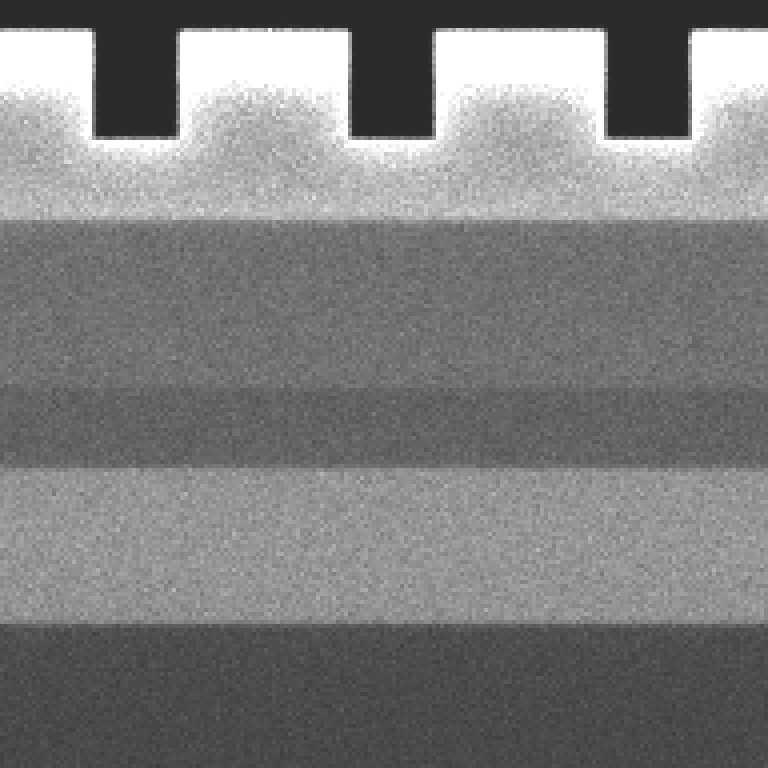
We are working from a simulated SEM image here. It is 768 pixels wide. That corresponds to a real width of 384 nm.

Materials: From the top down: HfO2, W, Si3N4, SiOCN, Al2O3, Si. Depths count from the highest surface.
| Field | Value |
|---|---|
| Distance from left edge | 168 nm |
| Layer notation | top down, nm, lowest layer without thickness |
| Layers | HfO2 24, W 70, Si3N4 84, SiOCN 40, Al2O3 78, Si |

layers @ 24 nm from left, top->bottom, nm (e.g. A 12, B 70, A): HfO2 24, W 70, Si3N4 84, SiOCN 40, Al2O3 78, Si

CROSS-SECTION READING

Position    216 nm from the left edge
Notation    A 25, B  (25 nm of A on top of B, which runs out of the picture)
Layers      empty 54, W 40, Si3N4 84, SiOCN 40, Al2O3 78, Si